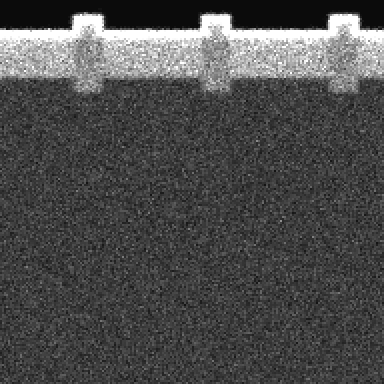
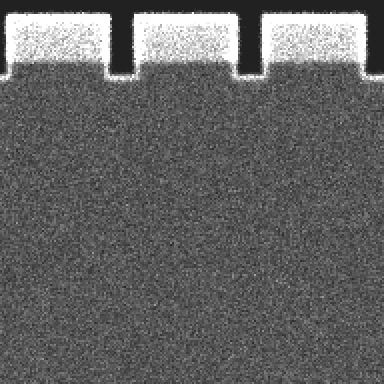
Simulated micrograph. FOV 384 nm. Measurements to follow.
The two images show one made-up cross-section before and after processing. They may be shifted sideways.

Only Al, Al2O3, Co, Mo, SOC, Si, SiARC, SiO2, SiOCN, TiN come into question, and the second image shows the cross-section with SOC removed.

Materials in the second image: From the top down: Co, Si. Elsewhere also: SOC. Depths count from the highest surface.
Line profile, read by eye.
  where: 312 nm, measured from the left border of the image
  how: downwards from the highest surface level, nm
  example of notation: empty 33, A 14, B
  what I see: Co 46, Si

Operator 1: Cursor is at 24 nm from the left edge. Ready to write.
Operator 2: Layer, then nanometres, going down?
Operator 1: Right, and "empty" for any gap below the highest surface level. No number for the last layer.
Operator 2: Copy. Co 46, Si